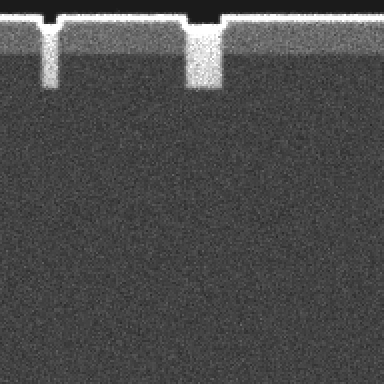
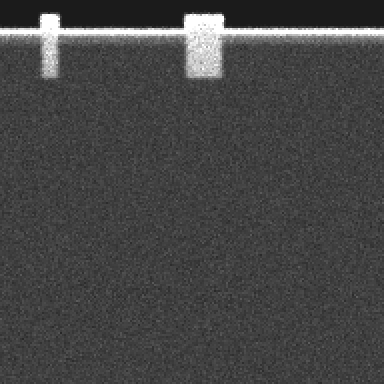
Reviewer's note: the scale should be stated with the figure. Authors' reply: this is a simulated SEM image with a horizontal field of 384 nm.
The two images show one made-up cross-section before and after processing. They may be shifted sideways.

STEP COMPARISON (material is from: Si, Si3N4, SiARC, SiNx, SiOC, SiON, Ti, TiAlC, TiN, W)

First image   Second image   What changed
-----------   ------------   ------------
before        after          SiNx, removed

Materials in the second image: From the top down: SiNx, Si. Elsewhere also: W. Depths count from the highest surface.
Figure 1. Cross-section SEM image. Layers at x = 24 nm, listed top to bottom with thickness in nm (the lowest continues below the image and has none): empty 14, SiNx 14, Si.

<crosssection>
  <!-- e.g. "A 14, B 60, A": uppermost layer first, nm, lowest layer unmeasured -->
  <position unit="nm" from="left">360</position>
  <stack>empty 14, SiNx 14, Si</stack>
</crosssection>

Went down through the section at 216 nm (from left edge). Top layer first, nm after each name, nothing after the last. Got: W 62, Si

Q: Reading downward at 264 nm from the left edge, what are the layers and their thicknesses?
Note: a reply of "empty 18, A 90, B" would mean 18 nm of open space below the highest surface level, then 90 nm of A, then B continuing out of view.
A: empty 14, SiNx 14, Si